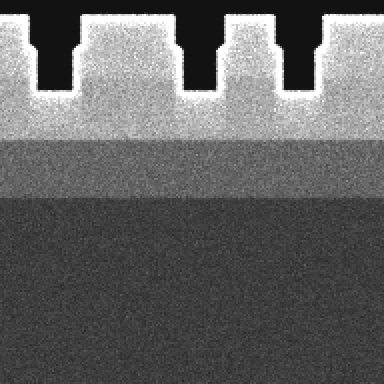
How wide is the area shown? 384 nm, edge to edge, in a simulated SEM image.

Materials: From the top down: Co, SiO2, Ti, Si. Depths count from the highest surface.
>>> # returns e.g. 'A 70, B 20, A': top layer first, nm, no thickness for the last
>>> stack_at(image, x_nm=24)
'Co 62, SiO2 62, Ti 58, Si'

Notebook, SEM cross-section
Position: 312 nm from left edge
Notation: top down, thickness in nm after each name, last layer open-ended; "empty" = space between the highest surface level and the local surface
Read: empty 76, Co 38, SiO2 10, Ti 58, Si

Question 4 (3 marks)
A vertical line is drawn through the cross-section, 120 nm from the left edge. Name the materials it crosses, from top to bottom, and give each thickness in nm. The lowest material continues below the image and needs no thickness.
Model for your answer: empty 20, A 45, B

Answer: Co 62, SiO2 62, Ti 58, Si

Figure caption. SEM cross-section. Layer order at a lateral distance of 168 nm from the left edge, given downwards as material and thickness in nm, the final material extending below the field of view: Co 62, SiO2 62, Ti 58, Si